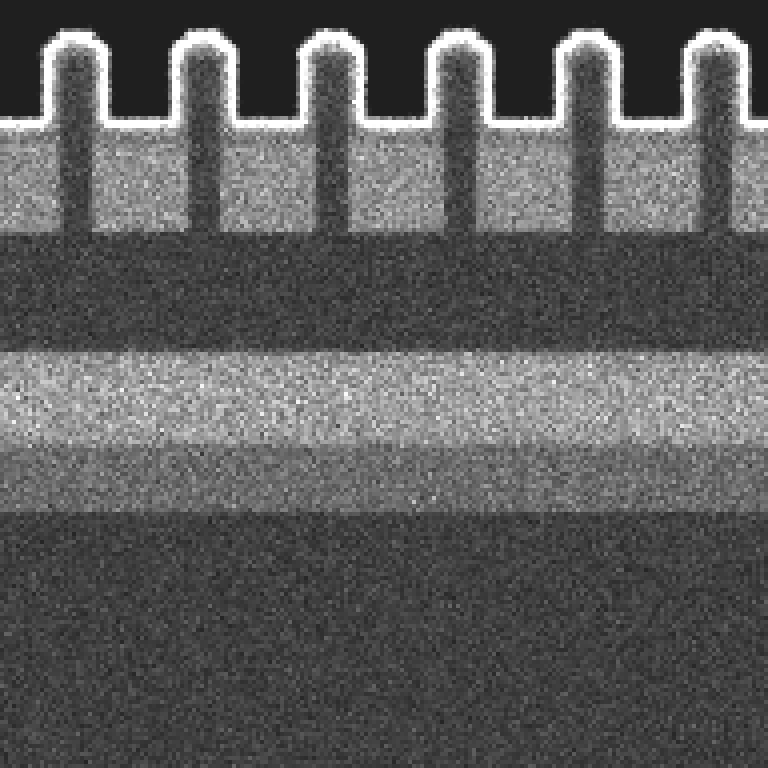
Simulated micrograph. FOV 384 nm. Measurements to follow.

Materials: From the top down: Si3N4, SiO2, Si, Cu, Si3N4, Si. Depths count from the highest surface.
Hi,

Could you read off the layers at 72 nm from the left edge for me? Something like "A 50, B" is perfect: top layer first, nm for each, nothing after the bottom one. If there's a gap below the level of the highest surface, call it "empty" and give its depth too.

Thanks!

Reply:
empty 44, Si3N4 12, SiO2 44, Si 60, Cu 46, Si3N4 34, Si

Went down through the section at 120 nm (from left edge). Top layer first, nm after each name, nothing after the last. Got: empty 44, Si3N4 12, SiO2 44, Si 60, Cu 46, Si3N4 34, Si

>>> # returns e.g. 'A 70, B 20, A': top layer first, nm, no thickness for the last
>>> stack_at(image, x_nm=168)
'Si3N4 12, Si 148, Cu 46, Si3N4 34, Si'